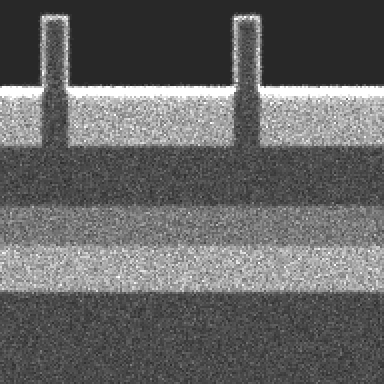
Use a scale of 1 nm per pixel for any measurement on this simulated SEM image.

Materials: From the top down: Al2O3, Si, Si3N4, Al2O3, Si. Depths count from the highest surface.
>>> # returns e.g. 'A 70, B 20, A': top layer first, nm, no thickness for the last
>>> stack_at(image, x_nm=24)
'empty 72, Al2O3 58, Si 60, Si3N4 40, Al2O3 46, Si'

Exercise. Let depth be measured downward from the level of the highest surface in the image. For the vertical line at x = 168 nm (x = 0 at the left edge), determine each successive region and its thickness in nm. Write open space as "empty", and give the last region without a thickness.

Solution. empty 72, Al2O3 58, Si 60, Si3N4 40, Al2O3 46, Si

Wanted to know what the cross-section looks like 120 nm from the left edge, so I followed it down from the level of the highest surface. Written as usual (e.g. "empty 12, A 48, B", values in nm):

empty 72, Al2O3 58, Si 60, Si3N4 40, Al2O3 46, Si